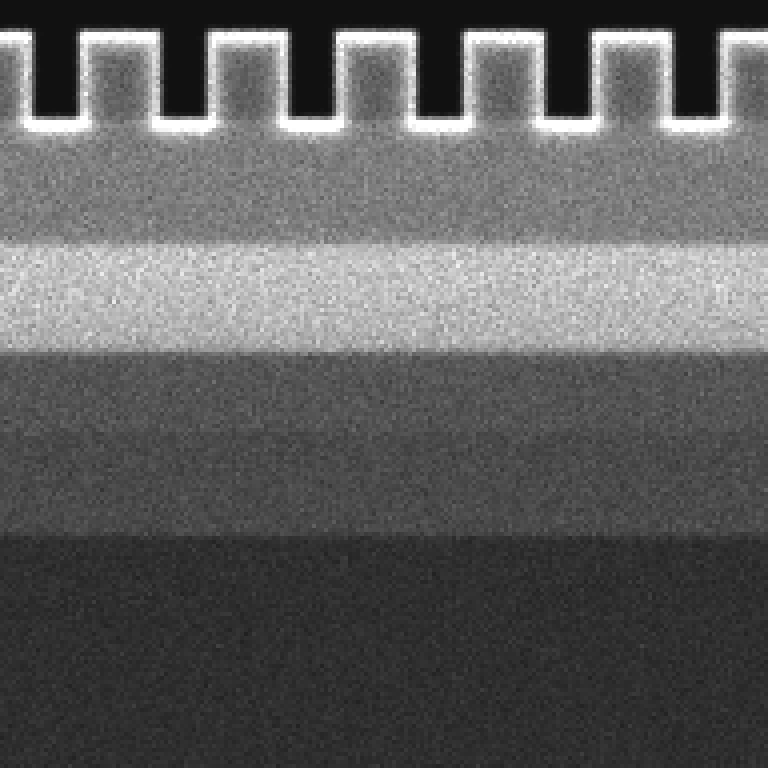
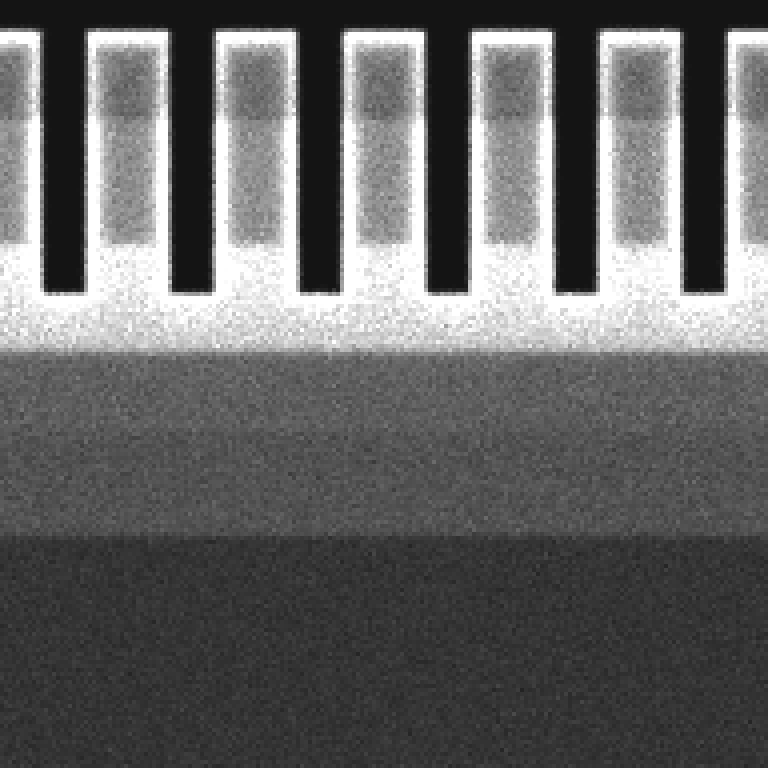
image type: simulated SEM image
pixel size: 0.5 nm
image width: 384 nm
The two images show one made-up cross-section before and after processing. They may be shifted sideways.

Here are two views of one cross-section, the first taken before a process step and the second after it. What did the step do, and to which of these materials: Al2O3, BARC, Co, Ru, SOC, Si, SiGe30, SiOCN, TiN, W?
It removed Al2O3 and W.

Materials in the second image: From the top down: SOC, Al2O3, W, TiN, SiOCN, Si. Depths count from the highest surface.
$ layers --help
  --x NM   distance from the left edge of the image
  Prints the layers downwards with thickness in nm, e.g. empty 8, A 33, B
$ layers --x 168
empty 132, W 28, TiN 40, SiOCN 52, Si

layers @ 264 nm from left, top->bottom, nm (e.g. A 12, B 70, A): SOC 44, Al2O3 62, W 54, TiN 40, SiOCN 52, Si